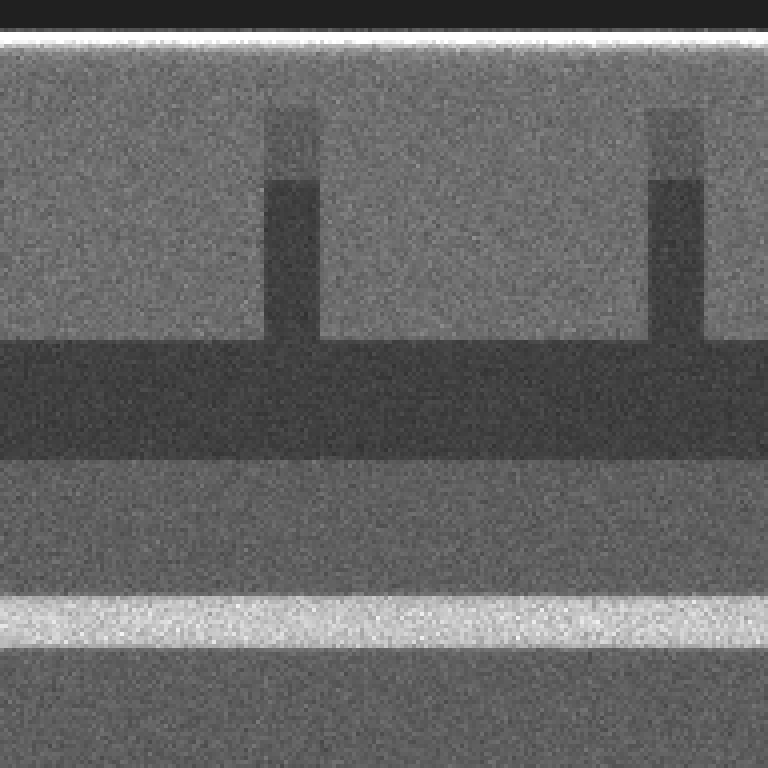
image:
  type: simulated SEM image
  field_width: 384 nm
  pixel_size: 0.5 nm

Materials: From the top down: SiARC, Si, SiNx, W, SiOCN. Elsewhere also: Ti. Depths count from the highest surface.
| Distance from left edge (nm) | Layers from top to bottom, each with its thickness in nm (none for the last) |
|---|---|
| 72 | SiARC 154, Si 60, SiNx 68, W 26, SiOCN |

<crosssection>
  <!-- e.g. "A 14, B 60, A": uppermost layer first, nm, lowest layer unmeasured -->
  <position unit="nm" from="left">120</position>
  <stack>SiARC 154, Si 60, SiNx 68, W 26, SiOCN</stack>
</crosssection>